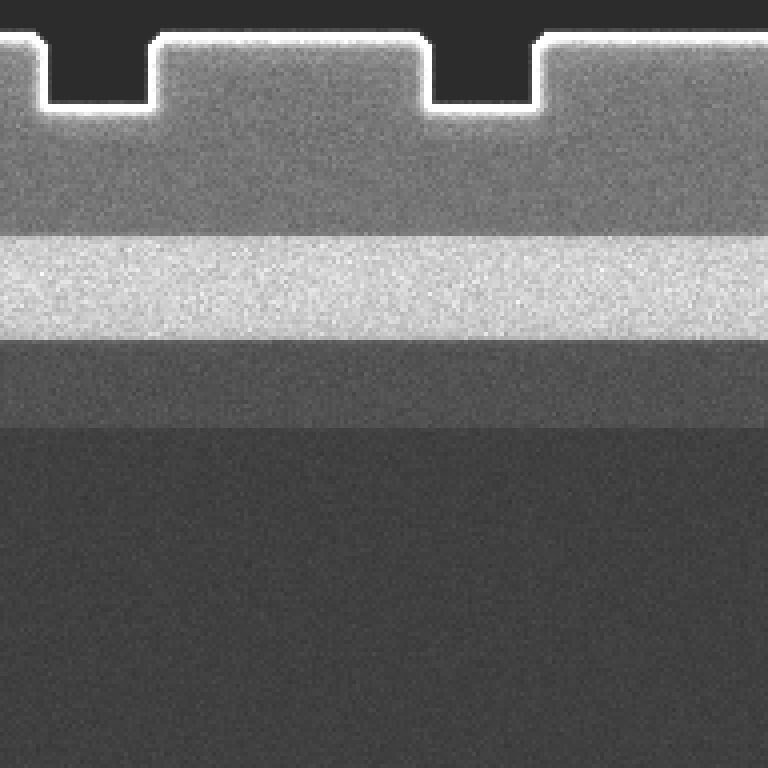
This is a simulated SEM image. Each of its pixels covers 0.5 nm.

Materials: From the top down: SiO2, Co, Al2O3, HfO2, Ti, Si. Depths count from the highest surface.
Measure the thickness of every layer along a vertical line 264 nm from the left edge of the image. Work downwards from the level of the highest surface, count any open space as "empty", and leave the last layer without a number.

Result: empty 36, SiO2 12, Co 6, Al2O3 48, HfO2 52, Ti 44, Si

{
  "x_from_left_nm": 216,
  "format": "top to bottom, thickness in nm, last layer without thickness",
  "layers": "empty 36, SiO2 12, Co 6, Al2O3 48, HfO2 52, Ti 44, Si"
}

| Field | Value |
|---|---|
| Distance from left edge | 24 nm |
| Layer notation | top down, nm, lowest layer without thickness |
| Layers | empty 36, SiO2 12, Co 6, Al2O3 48, HfO2 52, Ti 44, Si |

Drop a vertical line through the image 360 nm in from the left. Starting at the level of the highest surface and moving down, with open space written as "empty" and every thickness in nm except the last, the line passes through SiO2 12, Co 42, Al2O3 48, HfO2 52, Ti 44, Si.